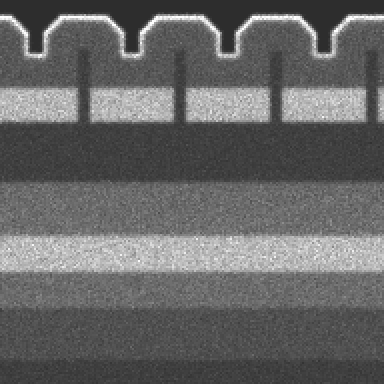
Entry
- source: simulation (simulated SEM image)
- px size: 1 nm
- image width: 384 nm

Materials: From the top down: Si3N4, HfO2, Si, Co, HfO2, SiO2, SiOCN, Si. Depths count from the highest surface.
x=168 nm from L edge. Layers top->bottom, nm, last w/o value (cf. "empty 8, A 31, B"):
Si3N4 72, HfO2 34, Si 60, Co 54, HfO2 36, SiO2 36, SiOCN 52, Si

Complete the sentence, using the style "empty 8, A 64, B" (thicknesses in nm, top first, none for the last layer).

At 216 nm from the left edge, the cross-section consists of empty 14, Si3N4 58, HfO2 34, Si 60, Co 54, HfO2 36, SiO2 36, SiOCN 52, Si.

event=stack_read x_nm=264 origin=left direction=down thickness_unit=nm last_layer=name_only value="Si3N4 72, HfO2 34, Si 60, Co 54, HfO2 36, SiO2 36, SiOCN 52, Si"